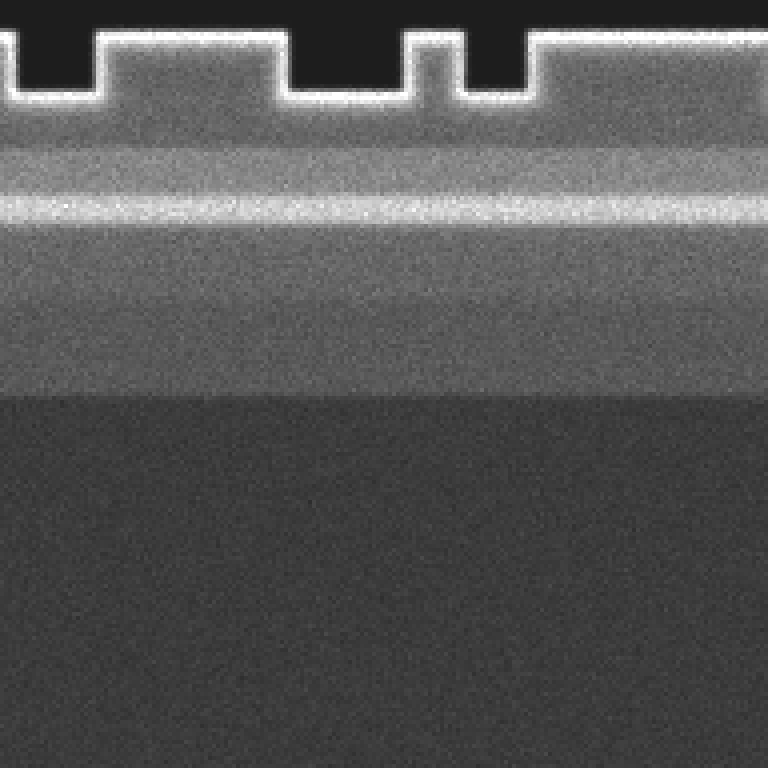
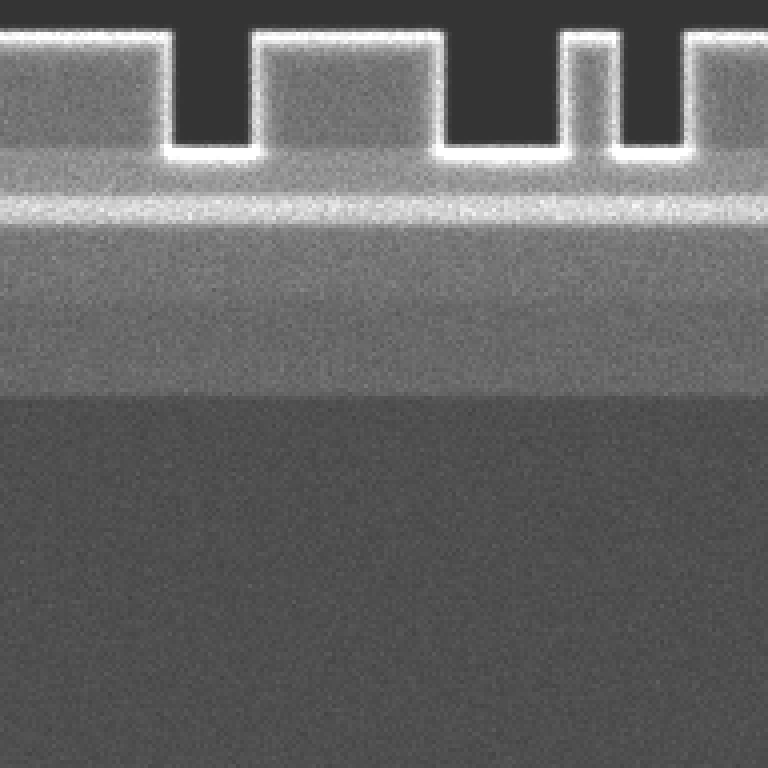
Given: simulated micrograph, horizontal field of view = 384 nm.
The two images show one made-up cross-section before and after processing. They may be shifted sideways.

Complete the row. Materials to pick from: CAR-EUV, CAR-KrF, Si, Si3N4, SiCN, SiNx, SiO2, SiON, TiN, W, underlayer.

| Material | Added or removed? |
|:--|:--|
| underlayer | removed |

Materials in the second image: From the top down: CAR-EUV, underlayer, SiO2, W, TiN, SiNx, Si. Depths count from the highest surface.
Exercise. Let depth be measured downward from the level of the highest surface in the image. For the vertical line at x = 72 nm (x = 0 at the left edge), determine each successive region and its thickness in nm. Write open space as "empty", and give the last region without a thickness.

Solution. CAR-EUV 30, underlayer 28, SiO2 24, W 14, TiN 38, SiNx 48, Si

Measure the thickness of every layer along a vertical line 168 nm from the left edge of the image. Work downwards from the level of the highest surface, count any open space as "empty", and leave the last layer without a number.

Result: CAR-EUV 30, underlayer 28, SiO2 24, W 14, TiN 38, SiNx 48, Si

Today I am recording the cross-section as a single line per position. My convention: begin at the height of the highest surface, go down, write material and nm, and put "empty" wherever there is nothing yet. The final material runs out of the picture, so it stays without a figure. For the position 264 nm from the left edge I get empty 58, SiO2 24, W 14, TiN 38, SiNx 48, Si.